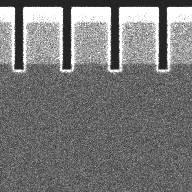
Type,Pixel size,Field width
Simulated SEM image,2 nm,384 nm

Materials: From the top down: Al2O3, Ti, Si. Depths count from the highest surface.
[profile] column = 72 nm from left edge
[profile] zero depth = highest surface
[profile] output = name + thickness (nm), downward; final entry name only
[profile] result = Al2O3 28, Ti 84, Si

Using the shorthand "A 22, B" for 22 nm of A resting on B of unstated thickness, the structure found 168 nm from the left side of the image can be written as Al2O3 28, Ti 84, Si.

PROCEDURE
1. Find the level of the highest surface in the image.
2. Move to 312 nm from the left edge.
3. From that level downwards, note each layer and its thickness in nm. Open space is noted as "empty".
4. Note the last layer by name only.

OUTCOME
Al2O3 28, Ti 84, Si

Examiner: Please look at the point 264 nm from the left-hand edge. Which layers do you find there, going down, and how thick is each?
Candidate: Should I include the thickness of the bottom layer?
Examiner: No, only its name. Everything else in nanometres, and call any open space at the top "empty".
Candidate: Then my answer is Al2O3 28, Ti 84, Si